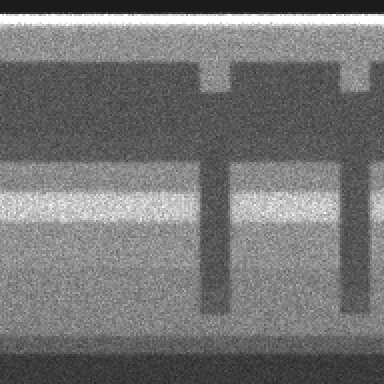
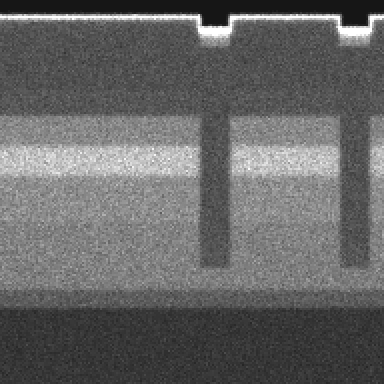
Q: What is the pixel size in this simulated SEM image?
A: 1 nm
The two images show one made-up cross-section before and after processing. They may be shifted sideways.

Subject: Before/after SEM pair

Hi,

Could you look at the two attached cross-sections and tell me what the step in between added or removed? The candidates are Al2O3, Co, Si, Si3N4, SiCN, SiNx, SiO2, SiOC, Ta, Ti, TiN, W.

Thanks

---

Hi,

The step removed Al2O3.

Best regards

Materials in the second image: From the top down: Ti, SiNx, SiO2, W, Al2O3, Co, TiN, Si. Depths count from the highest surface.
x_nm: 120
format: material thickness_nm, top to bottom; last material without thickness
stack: Ti 74, SiNx 26, SiO2 30, W 30, Al2O3 46, Co 68, TiN 18, Si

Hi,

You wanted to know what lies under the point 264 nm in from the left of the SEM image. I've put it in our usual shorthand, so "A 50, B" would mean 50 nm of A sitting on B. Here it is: Ti 74, SiNx 26, SiO2 30, W 30, Al2O3 46, Co 68, TiN 18, Si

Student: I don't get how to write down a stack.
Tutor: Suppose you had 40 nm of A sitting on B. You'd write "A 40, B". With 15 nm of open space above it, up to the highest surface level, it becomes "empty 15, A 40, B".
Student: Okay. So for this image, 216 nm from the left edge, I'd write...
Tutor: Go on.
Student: empty 12, Al2O3 18, Ti 196, SiNx 26, Co 22, TiN 18, Si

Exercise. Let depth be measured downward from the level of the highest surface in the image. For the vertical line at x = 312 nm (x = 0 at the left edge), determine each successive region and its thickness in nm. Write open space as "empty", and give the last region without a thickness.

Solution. Ti 74, SiNx 26, SiO2 30, W 30, Al2O3 46, Co 68, TiN 18, Si